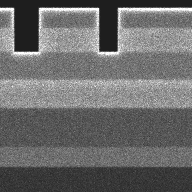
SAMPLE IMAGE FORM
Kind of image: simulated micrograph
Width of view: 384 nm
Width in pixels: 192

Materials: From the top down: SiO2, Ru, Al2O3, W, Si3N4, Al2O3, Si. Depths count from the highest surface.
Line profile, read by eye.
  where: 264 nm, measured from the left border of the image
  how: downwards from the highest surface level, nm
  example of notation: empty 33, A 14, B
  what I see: SiO2 40, Ru 48, Al2O3 56, W 56, Si3N4 78, Al2O3 40, Si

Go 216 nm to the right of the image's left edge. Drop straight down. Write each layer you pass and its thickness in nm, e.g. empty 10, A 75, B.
empty 88, Al2O3 56, W 56, Si3N4 78, Al2O3 40, Si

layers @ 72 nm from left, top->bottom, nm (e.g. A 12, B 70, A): empty 88, Al2O3 56, W 56, Si3N4 78, Al2O3 40, Si